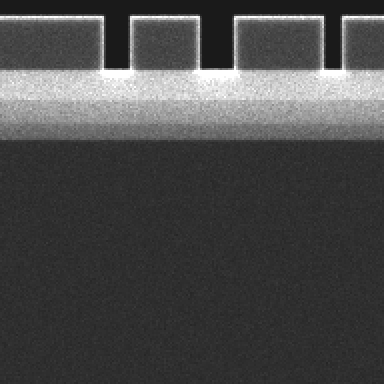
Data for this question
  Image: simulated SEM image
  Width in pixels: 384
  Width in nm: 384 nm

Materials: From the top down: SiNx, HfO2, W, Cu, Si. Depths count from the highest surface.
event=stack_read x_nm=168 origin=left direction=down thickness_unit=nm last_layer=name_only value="SiNx 54, HfO2 30, W 24, Cu 16, Si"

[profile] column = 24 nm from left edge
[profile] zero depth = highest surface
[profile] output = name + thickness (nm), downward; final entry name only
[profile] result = SiNx 54, HfO2 30, W 24, Cu 16, Si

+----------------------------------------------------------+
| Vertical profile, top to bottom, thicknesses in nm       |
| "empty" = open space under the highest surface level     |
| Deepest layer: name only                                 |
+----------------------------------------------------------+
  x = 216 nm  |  empty 54, HfO2 30, W 24, Cu 16, Si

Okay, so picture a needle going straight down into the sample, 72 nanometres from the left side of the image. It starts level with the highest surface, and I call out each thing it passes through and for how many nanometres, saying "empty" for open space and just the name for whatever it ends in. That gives SiNx 54, HfO2 30, W 24, Cu 16, Si